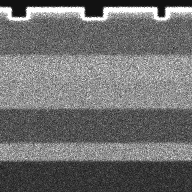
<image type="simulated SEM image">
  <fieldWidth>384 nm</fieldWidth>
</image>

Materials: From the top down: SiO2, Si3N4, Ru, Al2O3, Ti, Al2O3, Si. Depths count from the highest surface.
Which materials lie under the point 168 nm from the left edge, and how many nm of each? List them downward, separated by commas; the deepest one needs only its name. empty 20, Si3N4 74, Ru 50, Al2O3 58, Ti 68, Al2O3 36, Si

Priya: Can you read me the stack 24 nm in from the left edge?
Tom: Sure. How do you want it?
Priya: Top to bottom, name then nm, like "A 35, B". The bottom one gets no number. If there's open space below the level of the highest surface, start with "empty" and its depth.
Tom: empty 20, Si3N4 74, Ru 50, Al2O3 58, Ti 68, Al2O3 36, Si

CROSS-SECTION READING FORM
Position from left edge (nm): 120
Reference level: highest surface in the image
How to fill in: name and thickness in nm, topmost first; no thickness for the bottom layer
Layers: SiO2 20, Si3N4 74, Ru 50, Al2O3 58, Ti 68, Al2O3 36, Si